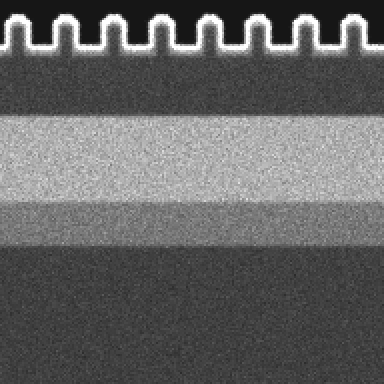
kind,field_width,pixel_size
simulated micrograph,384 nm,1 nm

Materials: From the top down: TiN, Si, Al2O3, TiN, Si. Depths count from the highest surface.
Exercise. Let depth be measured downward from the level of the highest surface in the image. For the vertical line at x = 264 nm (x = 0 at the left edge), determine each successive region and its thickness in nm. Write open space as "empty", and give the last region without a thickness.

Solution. empty 4, TiN 36, Si 60, Al2O3 86, TiN 44, Si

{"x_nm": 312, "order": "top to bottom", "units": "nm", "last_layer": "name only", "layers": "empty 4, TiN 36, Si 60, Al2O3 86, TiN 44, Si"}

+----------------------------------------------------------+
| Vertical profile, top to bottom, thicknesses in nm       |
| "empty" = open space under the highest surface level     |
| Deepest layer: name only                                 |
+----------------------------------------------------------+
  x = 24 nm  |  empty 4, TiN 36, Si 60, Al2O3 86, TiN 44, Si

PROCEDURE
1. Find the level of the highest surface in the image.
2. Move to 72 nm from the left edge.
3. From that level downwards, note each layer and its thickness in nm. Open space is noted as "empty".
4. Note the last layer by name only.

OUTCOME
empty 4, TiN 36, Si 60, Al2O3 86, TiN 44, Si